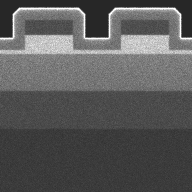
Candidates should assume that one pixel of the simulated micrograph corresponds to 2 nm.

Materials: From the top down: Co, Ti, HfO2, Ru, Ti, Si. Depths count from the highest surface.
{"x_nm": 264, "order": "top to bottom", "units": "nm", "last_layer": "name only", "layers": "Co 24, Ti 30, HfO2 38, Ru 74, Ti 76, Si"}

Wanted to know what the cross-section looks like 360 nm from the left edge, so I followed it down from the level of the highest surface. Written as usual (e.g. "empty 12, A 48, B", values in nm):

empty 12, Co 72, HfO2 8, Ru 74, Ti 76, Si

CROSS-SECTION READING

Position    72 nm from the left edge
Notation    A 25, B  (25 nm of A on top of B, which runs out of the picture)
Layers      Co 24, Ti 30, HfO2 38, Ru 74, Ti 76, Si